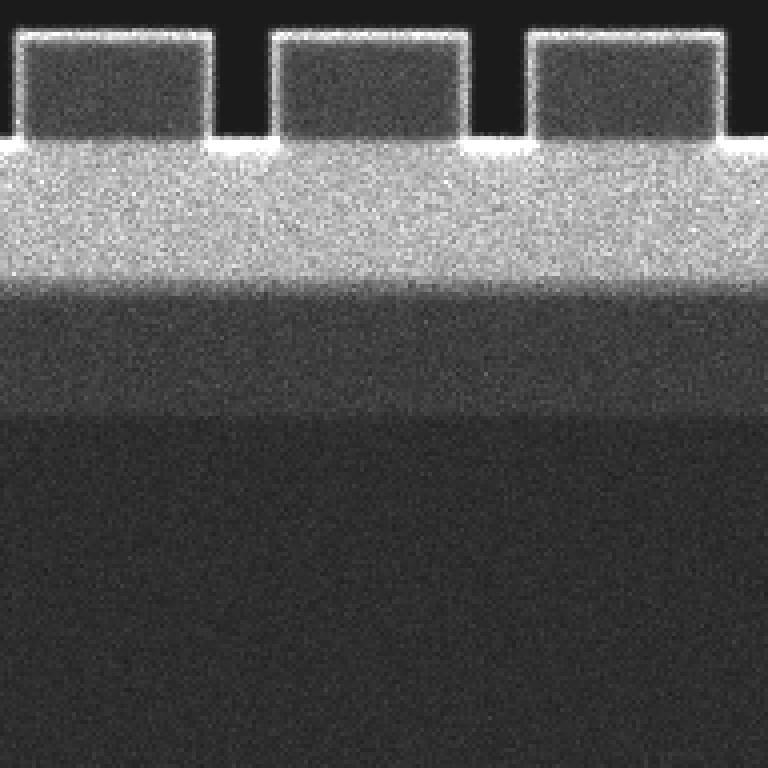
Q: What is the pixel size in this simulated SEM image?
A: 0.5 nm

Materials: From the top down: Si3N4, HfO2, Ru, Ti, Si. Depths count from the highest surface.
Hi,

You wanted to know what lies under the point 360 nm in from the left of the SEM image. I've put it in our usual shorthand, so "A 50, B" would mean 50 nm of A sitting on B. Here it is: Si3N4 54, HfO2 70, Ru 8, Ti 60, Si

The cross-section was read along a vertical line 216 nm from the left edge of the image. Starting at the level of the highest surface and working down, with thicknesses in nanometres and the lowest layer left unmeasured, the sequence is Si3N4 54, HfO2 70, Ru 8, Ti 60, Si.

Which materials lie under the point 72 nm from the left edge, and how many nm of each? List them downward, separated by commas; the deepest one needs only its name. Si3N4 54, HfO2 70, Ru 8, Ti 60, Si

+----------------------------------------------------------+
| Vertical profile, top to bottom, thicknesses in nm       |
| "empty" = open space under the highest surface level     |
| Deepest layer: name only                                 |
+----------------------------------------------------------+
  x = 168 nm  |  Si3N4 54, HfO2 70, Ru 8, Ti 60, Si